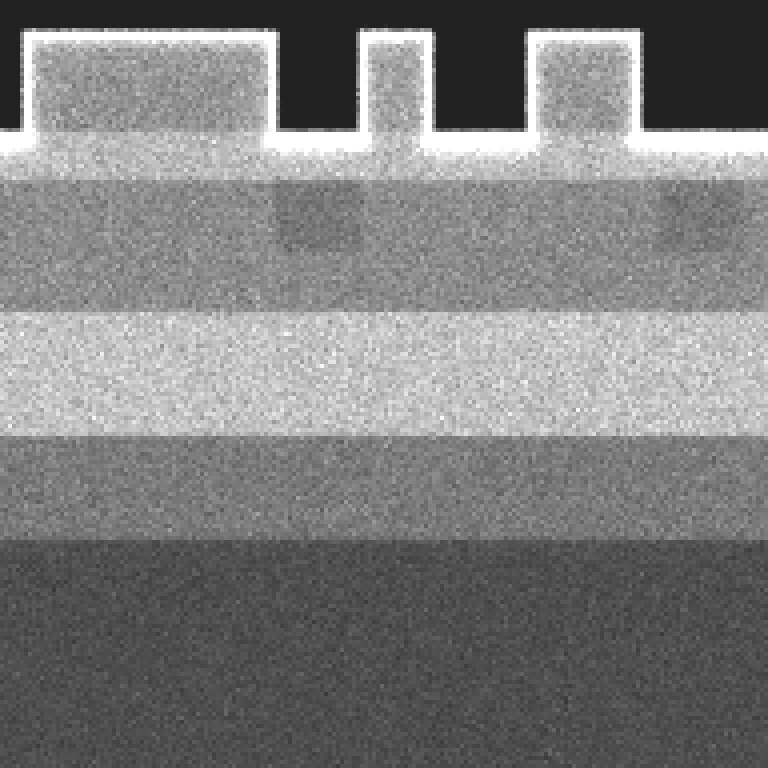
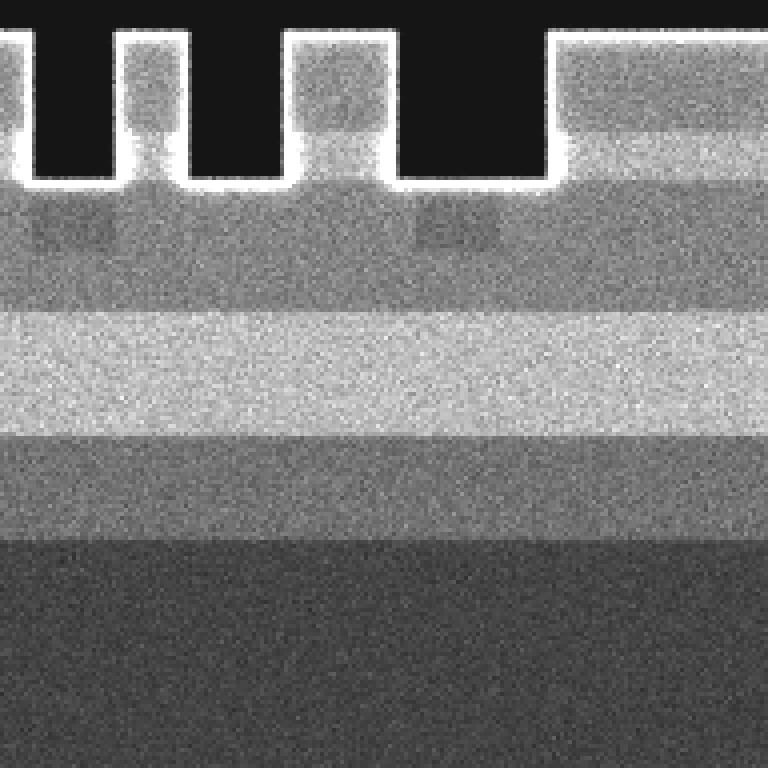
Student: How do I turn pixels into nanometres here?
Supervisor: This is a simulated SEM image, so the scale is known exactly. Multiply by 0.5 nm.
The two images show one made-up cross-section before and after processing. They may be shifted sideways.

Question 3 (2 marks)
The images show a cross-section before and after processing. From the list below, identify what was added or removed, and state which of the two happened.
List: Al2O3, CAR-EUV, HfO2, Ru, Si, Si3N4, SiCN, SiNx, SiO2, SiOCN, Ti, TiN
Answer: SiO2 was removed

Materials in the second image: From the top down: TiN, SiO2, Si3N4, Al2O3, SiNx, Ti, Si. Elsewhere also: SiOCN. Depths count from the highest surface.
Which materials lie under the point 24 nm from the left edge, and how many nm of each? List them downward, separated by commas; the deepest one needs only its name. empty 74, SiOCN 36, Si3N4 30, Al2O3 62, SiNx 28, Ti 24, Si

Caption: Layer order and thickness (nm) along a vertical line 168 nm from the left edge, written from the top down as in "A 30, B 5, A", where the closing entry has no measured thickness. TiN 50, SiO2 24, Si3N4 66, Al2O3 62, SiNx 28, Ti 24, Si